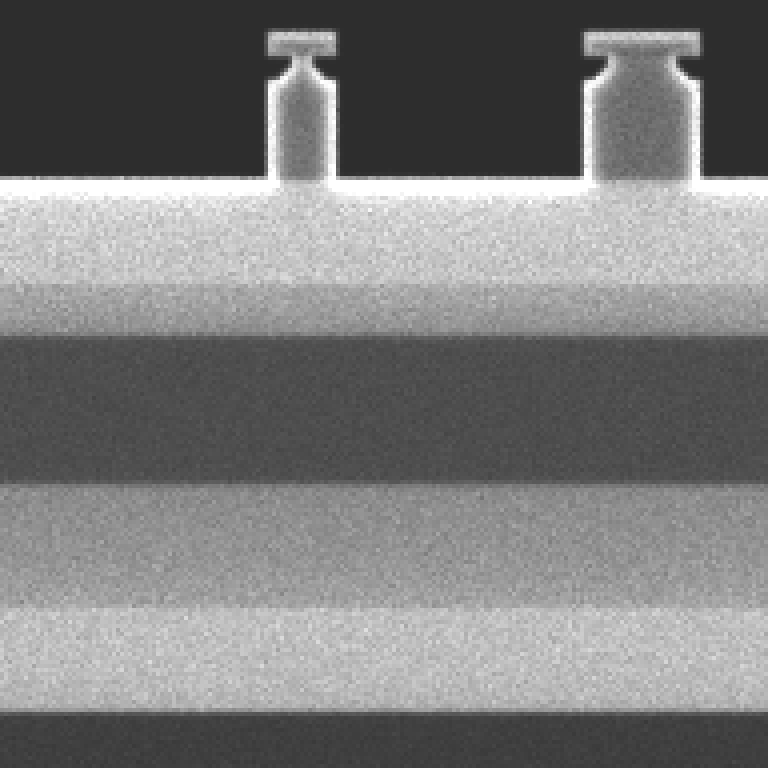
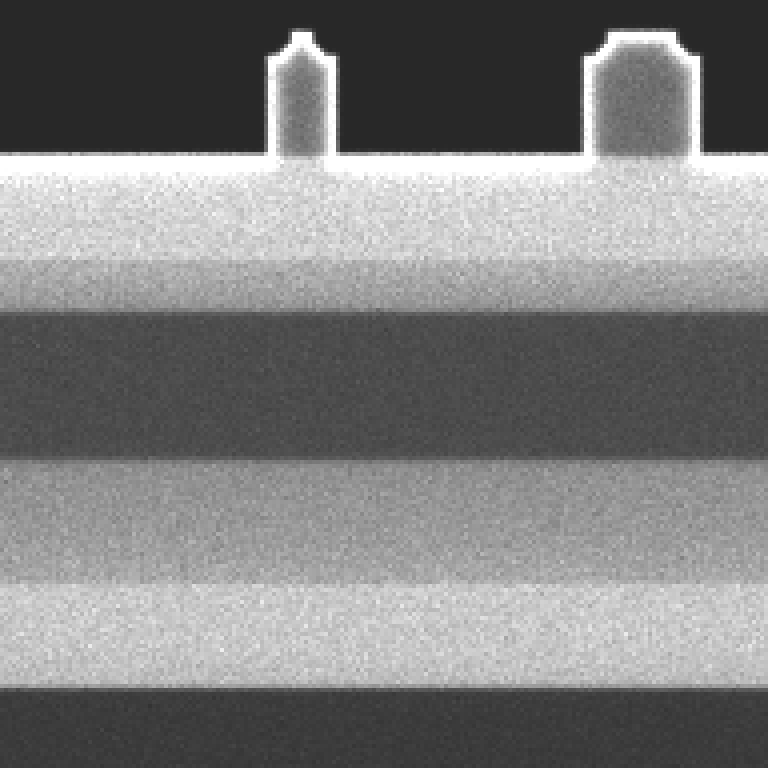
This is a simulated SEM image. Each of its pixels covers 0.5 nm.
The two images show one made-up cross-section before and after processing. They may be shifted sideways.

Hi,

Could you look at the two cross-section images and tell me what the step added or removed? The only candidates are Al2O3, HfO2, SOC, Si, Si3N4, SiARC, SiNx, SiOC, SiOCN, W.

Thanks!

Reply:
removed SOC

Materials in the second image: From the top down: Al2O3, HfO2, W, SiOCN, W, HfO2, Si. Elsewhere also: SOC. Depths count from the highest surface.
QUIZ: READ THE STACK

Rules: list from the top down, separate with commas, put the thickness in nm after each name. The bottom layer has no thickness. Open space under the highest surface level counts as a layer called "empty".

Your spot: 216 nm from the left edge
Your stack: empty 62, HfO2 52, W 26, SiOCN 74, W 62, HfO2 52, Si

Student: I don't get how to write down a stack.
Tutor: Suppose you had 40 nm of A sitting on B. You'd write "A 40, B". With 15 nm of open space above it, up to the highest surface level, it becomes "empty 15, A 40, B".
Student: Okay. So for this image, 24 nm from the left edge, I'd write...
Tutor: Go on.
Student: empty 62, HfO2 52, W 26, SiOCN 74, W 62, HfO2 52, Si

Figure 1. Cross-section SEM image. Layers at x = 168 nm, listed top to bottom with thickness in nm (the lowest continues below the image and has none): empty 62, HfO2 52, W 26, SiOCN 74, W 62, HfO2 52, Si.